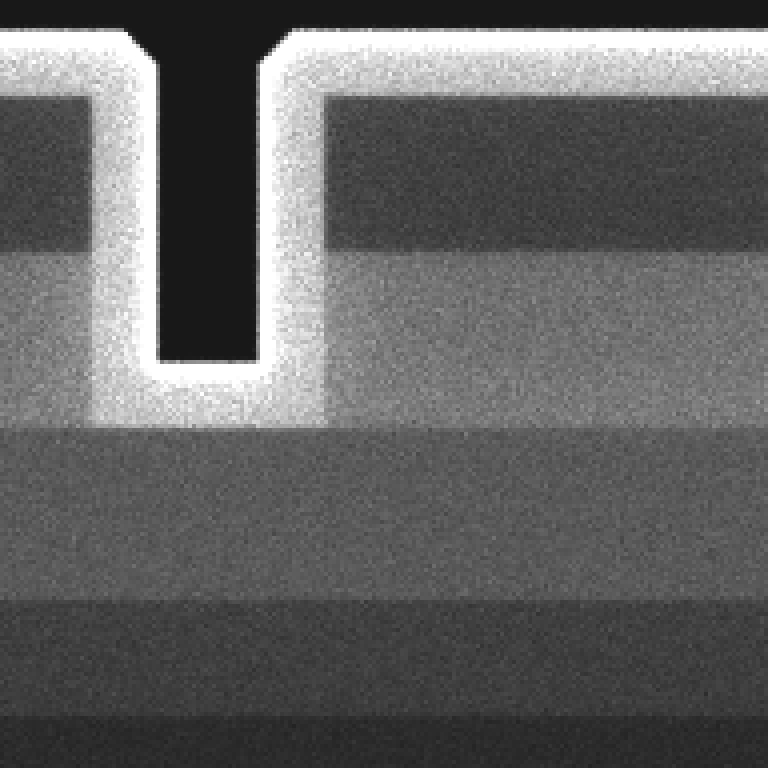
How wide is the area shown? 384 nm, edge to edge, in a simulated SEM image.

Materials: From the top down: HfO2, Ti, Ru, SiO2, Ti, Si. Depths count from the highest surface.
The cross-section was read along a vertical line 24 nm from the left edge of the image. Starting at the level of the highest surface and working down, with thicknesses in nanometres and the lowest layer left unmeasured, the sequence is HfO2 32, Ti 78, Ru 88, SiO2 86, Ti 58, Si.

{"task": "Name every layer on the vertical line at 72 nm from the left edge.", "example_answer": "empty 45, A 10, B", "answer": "empty 12, HfO2 186, SiO2 86, Ti 58, Si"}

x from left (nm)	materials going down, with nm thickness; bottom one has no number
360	HfO2 32, Ti 78, Ru 88, SiO2 86, Ti 58, Si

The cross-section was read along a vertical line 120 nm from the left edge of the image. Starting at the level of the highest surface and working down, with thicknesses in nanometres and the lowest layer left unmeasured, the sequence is empty 166, HfO2 32, SiO2 86, Ti 58, Si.